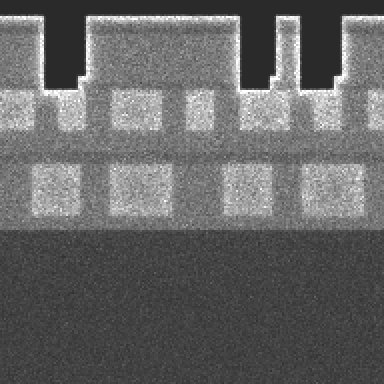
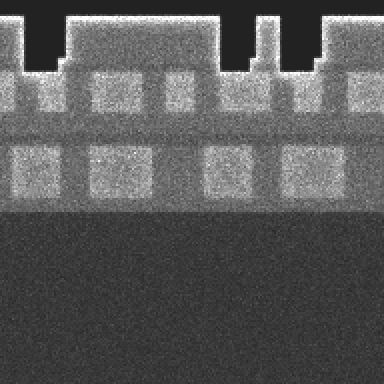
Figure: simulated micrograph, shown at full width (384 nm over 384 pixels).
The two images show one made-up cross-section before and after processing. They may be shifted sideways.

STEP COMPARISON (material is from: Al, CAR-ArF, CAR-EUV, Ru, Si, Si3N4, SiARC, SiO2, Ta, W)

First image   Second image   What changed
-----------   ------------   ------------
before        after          SiARC, removed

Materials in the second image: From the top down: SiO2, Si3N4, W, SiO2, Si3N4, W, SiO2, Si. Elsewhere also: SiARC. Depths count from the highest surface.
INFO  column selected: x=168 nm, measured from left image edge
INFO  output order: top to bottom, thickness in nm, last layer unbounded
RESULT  SiO2 48, Si3N4 8, W 40, SiO2 22, Si3N4 12, SiO2 66, Si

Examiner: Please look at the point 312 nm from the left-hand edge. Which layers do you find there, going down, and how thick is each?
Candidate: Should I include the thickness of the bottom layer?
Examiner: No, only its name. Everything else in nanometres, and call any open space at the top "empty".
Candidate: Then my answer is empty 56, W 40, SiO2 22, Si3N4 12, W 52, SiO2 14, Si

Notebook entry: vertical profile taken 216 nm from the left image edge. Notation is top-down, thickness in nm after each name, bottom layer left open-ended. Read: SiO2 48, Si3N4 8, SiO2 62, Si3N4 12, W 52, SiO2 14, Si